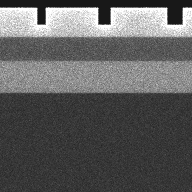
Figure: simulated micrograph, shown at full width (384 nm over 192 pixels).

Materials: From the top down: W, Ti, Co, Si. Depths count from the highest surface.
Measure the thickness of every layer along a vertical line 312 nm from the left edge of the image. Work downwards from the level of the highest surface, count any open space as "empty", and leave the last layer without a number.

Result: W 58, Ti 48, Co 64, Si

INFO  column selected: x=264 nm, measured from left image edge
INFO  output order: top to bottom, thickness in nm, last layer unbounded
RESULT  W 58, Ti 48, Co 64, Si